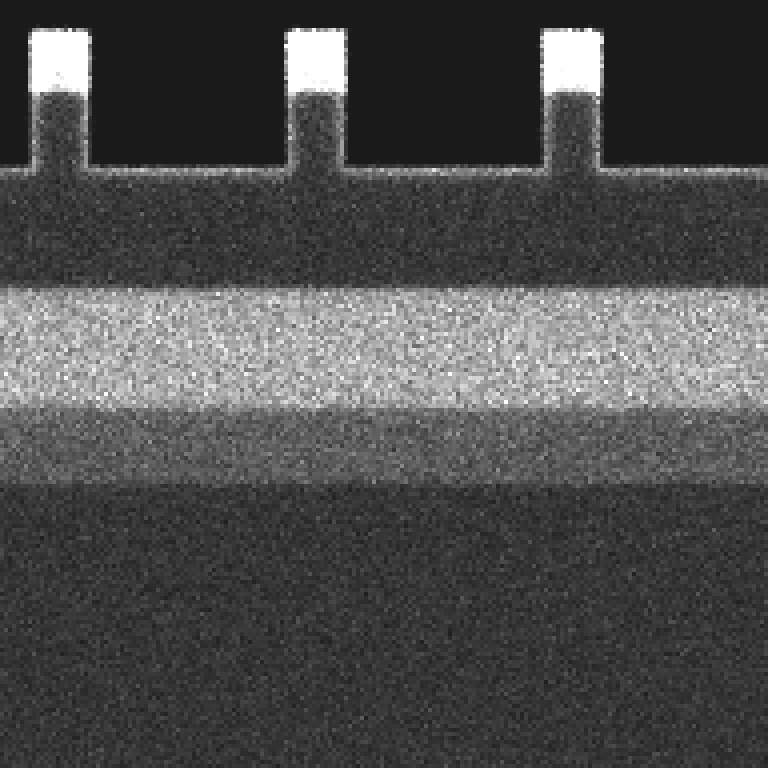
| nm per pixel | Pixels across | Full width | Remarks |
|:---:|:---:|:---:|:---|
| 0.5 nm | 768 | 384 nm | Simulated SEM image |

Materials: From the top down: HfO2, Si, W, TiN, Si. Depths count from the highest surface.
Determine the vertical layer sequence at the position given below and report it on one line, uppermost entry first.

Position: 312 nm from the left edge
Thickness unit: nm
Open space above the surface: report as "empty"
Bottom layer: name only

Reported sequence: empty 68, Si 60, W 60, TiN 38, Si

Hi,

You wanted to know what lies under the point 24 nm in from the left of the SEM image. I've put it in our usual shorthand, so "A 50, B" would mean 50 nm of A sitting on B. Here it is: HfO2 30, Si 98, W 60, TiN 38, Si